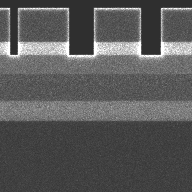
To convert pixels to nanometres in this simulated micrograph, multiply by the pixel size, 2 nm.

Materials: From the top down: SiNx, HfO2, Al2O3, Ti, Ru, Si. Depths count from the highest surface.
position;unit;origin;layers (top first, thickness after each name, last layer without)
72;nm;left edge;SiNx 68, HfO2 26, Al2O3 38, Ti 54, Ru 40, Si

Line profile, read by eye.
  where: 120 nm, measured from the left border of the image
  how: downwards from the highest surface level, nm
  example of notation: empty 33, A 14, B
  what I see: SiNx 68, HfO2 26, Al2O3 38, Ti 54, Ru 40, Si